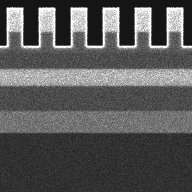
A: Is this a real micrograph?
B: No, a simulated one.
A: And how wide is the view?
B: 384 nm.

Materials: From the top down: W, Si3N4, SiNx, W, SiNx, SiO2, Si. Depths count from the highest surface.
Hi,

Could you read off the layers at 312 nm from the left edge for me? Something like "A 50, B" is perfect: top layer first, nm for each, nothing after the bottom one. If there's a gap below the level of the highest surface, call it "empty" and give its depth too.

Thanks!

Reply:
empty 76, Si3N4 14, SiNx 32, W 34, SiNx 50, SiO2 44, Si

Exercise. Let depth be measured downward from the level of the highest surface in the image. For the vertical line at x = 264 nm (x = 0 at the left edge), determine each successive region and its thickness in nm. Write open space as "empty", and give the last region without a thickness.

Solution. empty 76, Si3N4 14, SiNx 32, W 34, SiNx 50, SiO2 44, Si